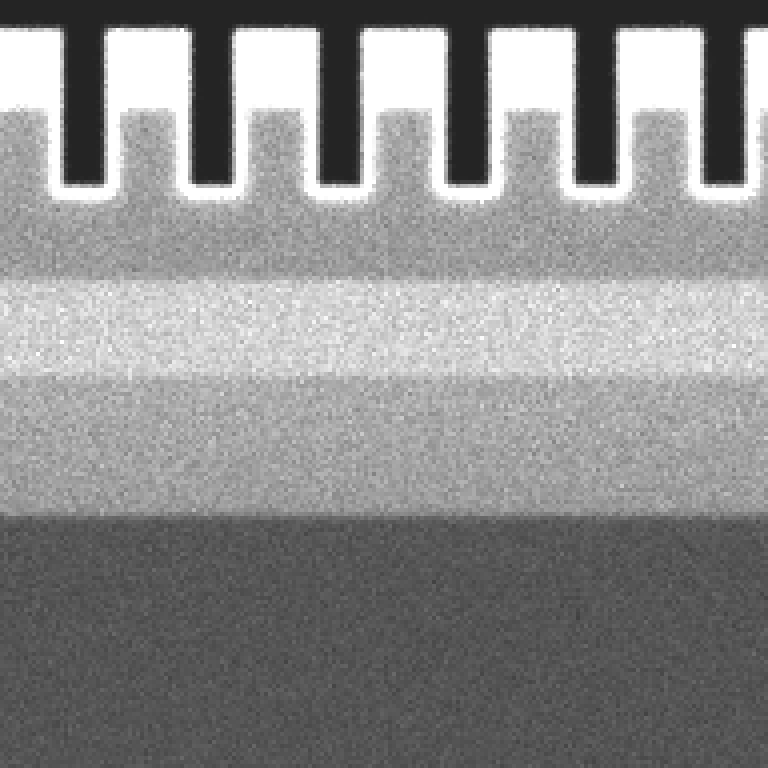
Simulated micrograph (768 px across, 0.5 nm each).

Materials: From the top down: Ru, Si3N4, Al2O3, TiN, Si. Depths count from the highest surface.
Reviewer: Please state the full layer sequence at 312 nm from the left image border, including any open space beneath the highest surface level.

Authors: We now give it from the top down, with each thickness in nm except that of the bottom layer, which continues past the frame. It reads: Ru 38, Si3N4 86, Al2O3 48, TiN 70, Si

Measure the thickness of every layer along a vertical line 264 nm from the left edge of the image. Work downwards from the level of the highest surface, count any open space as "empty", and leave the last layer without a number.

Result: Ru 38, Si3N4 86, Al2O3 48, TiN 70, Si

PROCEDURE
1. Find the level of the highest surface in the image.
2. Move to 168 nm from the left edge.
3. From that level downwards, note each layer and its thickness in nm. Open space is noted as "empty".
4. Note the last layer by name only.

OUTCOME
empty 78, Si3N4 46, Al2O3 48, TiN 70, Si